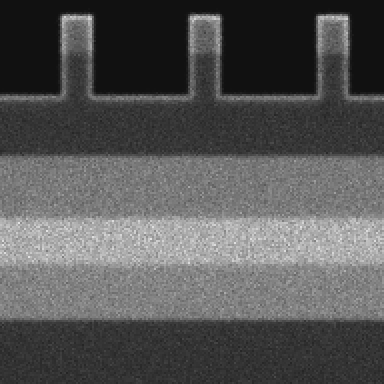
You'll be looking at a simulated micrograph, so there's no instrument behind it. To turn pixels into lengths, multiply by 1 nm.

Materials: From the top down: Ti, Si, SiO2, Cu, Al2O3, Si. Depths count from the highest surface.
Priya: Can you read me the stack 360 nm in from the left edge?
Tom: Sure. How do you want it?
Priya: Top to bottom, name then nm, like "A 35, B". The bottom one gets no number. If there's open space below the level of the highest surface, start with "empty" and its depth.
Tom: empty 80, Si 60, SiO2 62, Cu 46, Al2O3 56, Si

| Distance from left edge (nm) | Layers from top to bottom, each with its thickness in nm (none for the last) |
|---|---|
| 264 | empty 80, Si 60, SiO2 62, Cu 46, Al2O3 56, Si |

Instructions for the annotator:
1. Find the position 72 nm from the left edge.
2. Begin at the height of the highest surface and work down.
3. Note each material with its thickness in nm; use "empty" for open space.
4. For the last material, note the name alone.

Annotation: Ti 38, Si 102, SiO2 62, Cu 46, Al2O3 56, Si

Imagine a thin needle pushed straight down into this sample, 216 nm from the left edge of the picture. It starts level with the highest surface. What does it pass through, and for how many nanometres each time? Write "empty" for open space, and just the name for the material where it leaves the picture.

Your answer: Ti 38, Si 102, SiO2 62, Cu 46, Al2O3 56, Si